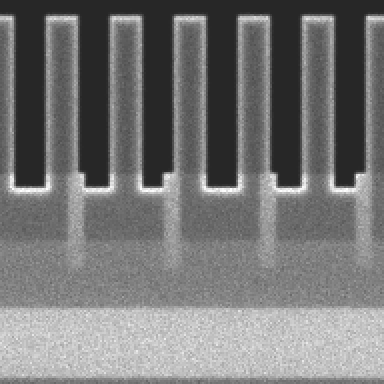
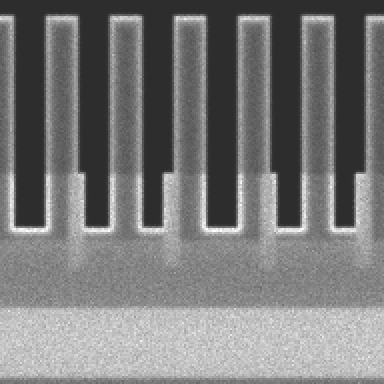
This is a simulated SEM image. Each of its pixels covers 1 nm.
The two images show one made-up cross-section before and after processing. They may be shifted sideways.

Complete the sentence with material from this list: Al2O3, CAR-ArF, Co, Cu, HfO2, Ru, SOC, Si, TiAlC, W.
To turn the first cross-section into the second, Al2O3 must be removed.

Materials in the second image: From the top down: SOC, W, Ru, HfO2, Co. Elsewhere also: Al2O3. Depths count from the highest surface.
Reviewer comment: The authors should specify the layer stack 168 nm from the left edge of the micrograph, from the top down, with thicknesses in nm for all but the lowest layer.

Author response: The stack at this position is empty 158, W 94, Ru 40, HfO2 70, Co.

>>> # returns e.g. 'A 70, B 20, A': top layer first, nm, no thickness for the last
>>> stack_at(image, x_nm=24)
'empty 212, Al2O3 12, Ru 68, HfO2 70, Co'